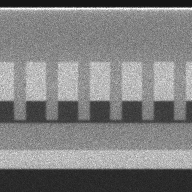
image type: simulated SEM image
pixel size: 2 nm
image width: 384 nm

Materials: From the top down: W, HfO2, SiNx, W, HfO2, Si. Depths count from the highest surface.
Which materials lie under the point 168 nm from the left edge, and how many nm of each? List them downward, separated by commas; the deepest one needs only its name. W 224, SiNx 6, W 54, HfO2 38, Si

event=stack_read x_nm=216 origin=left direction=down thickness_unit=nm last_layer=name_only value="W 108, HfO2 78, SiNx 44, W 54, HfO2 38, Si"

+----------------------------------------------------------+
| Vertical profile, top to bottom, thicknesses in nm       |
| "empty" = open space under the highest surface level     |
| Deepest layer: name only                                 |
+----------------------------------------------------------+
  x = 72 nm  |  W 108, HfO2 78, SiNx 44, W 54, HfO2 38, Si